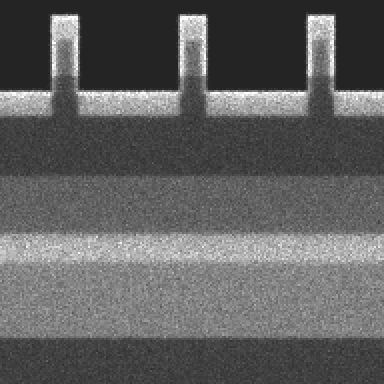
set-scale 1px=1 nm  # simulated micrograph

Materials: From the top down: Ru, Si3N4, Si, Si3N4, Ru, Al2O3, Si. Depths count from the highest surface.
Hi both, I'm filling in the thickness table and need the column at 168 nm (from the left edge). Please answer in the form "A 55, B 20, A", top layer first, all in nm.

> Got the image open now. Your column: empty 76, Ru 24, Si 60, Si3N4 58, Ru 28, Al2O3 76, Si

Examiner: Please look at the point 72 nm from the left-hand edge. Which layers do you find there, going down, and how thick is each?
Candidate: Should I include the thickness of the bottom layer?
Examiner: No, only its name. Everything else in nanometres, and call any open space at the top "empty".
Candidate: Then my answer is Ru 24, Si3N4 36, Si 100, Si3N4 58, Ru 28, Al2O3 76, Si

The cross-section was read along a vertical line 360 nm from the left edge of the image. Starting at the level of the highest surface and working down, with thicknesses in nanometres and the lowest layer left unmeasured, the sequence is empty 76, Ru 24, Si 60, Si3N4 58, Ru 28, Al2O3 76, Si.